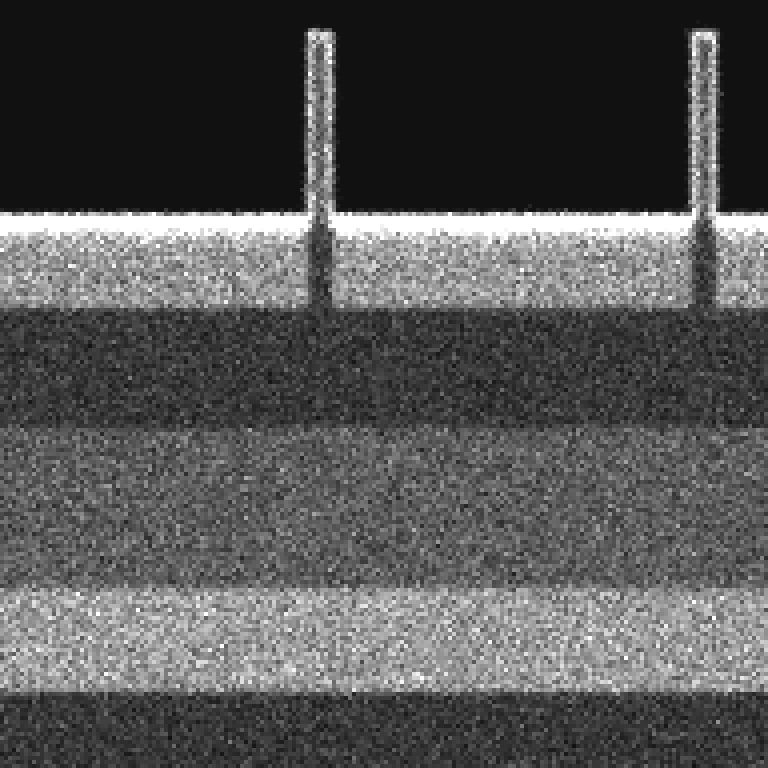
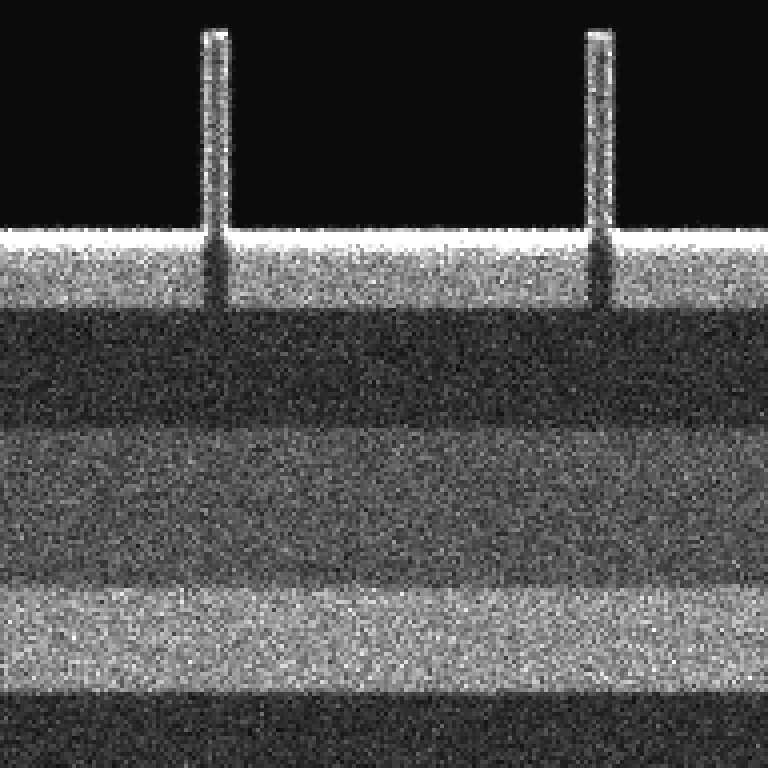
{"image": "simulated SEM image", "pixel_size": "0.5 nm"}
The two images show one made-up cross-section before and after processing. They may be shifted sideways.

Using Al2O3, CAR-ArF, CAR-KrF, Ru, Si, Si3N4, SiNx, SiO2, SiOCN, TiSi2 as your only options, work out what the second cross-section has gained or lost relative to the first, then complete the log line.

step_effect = removed SiO2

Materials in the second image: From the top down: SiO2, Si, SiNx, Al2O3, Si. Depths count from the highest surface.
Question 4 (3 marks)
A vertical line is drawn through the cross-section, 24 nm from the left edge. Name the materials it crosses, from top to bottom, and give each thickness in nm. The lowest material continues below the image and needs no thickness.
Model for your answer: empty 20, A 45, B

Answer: empty 100, SiO2 38, Si 60, SiNx 80, Al2O3 52, Si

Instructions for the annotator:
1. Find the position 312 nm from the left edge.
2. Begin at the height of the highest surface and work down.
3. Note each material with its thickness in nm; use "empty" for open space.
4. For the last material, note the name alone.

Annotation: empty 100, SiO2 38, Si 60, SiNx 80, Al2O3 52, Si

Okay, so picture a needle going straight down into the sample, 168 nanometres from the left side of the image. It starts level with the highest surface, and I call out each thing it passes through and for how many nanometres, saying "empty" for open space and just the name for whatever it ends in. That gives empty 100, SiO2 38, Si 60, SiNx 80, Al2O3 52, Si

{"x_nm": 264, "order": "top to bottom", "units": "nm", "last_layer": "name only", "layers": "empty 100, SiO2 38, Si 60, SiNx 80, Al2O3 52, Si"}